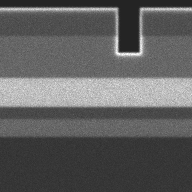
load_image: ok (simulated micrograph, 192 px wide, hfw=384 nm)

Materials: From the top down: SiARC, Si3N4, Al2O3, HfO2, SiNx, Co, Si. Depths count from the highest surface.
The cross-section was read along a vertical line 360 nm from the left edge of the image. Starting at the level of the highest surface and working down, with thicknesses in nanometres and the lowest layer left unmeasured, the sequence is SiARC 16, Si3N4 40, Al2O3 84, HfO2 58, SiNx 24, Co 36, Si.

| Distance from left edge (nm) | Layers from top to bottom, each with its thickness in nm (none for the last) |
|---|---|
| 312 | SiARC 16, Si3N4 40, Al2O3 84, HfO2 58, SiNx 24, Co 36, Si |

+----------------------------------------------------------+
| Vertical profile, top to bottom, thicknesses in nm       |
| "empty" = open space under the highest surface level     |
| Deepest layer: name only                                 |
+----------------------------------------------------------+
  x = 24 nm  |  SiARC 16, Si3N4 40, Al2O3 84, HfO2 58, SiNx 24, Co 36, Si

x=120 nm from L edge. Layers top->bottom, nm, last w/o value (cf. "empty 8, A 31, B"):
SiARC 16, Si3N4 40, Al2O3 84, HfO2 58, SiNx 24, Co 36, Si